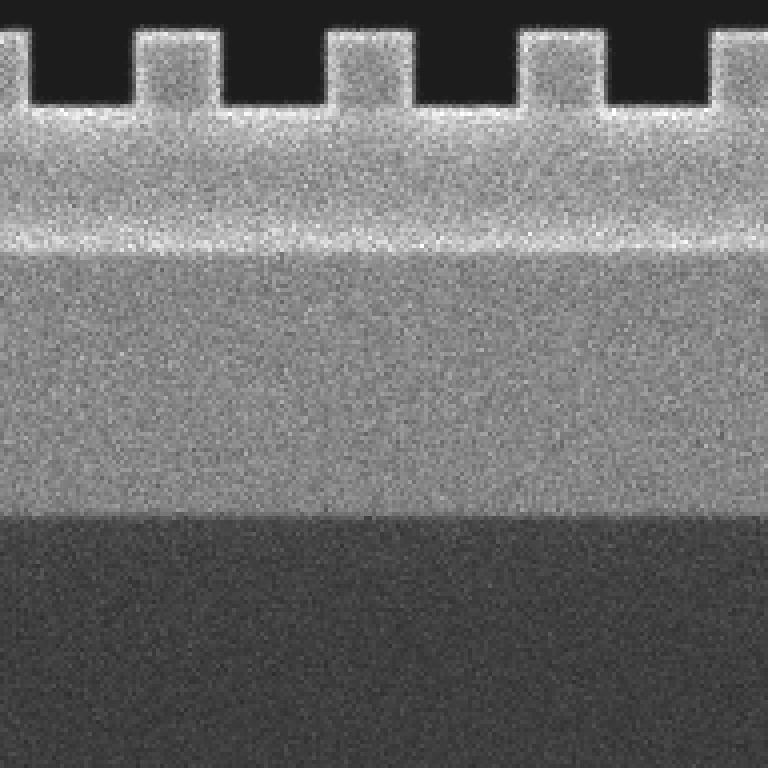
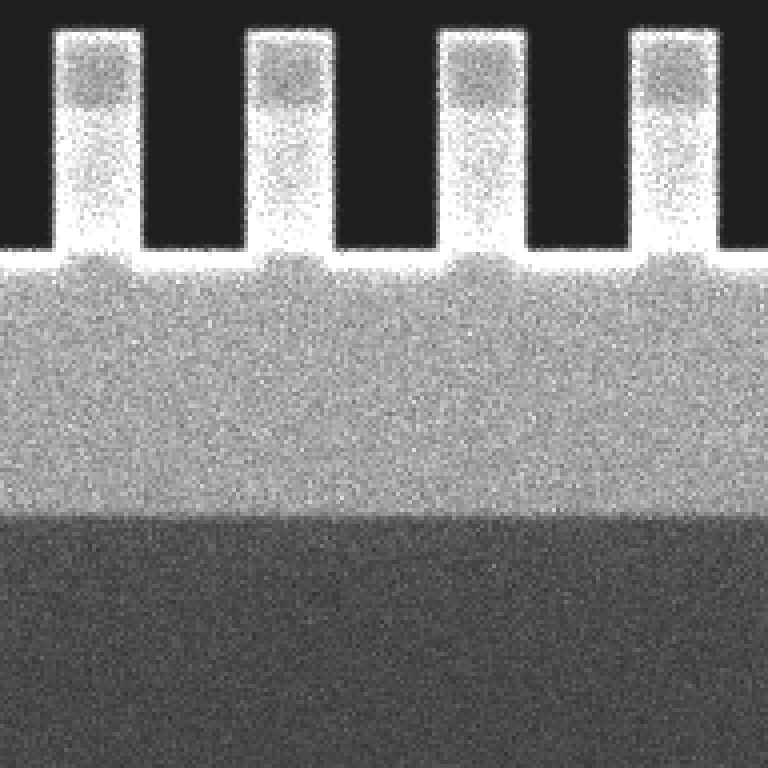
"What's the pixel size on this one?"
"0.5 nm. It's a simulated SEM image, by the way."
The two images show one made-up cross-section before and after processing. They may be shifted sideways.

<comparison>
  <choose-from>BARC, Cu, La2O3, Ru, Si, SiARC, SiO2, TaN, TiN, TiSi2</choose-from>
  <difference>Ru removed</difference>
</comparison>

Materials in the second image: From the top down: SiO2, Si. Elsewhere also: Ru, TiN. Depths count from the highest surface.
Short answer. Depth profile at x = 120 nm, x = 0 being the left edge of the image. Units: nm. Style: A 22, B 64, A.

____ empty 110, SiO2 132, Si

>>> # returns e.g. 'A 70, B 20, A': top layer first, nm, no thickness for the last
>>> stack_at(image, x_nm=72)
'empty 110, SiO2 132, Si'